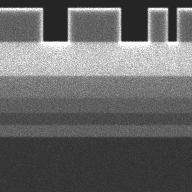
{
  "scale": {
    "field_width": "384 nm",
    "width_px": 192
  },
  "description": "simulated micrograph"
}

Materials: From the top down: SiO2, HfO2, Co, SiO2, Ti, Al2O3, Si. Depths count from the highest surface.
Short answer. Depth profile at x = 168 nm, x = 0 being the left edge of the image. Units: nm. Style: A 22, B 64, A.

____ SiO2 68, HfO2 68, Co 44, SiO2 30, Ti 24, Al2O3 24, Si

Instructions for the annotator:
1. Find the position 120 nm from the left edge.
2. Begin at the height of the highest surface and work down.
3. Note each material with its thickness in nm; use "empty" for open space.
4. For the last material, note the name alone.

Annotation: empty 68, HfO2 68, Co 44, SiO2 30, Ti 24, Al2O3 24, Si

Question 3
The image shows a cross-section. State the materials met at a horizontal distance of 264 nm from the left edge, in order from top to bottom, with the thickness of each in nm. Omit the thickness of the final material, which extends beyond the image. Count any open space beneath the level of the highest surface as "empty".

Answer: empty 68, HfO2 68, Co 44, SiO2 30, Ti 24, Al2O3 24, Si